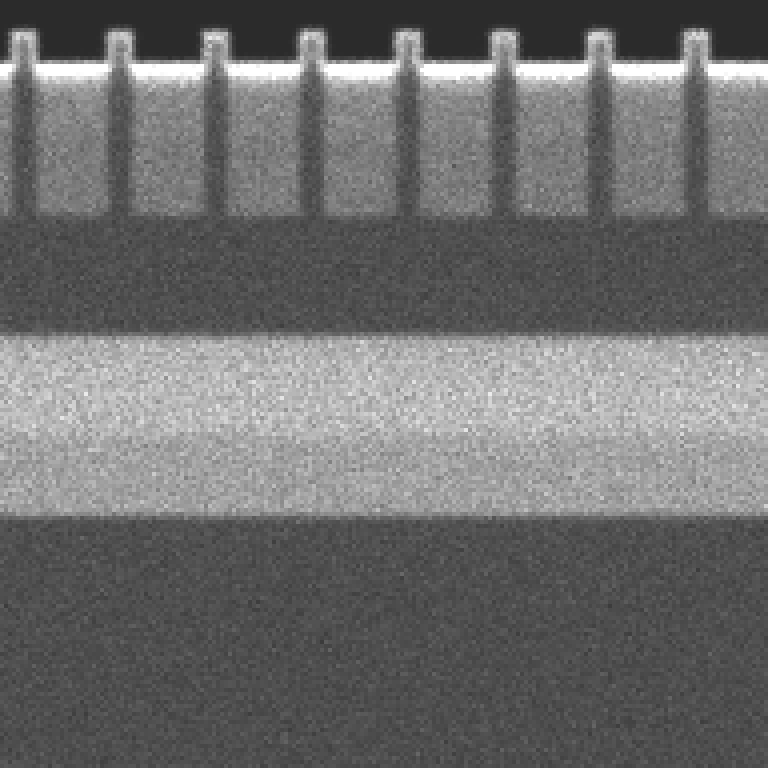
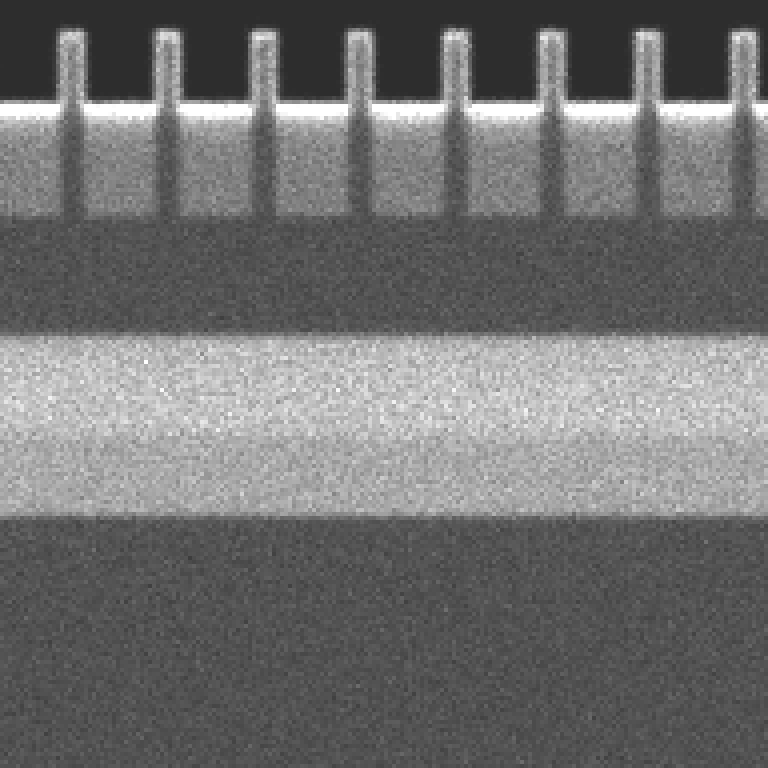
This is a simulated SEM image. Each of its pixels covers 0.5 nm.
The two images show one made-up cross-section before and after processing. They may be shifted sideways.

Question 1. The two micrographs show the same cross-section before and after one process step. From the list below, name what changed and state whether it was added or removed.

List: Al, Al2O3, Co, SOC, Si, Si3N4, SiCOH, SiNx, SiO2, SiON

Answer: SOC, removed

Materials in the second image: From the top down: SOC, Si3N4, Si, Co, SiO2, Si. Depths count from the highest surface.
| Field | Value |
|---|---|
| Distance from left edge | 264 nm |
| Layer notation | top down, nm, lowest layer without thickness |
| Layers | empty 36, SOC 16, Si3N4 40, Si 60, Co 50, SiO2 40, Si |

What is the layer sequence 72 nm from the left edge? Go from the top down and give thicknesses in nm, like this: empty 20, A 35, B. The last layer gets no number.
empty 36, SOC 16, Si3N4 40, Si 60, Co 50, SiO2 40, Si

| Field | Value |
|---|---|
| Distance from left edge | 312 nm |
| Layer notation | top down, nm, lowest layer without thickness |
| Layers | empty 36, SOC 16, Si3N4 40, Si 60, Co 50, SiO2 40, Si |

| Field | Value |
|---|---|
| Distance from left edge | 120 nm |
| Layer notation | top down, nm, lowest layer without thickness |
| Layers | empty 36, SOC 16, Si3N4 40, Si 60, Co 50, SiO2 40, Si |